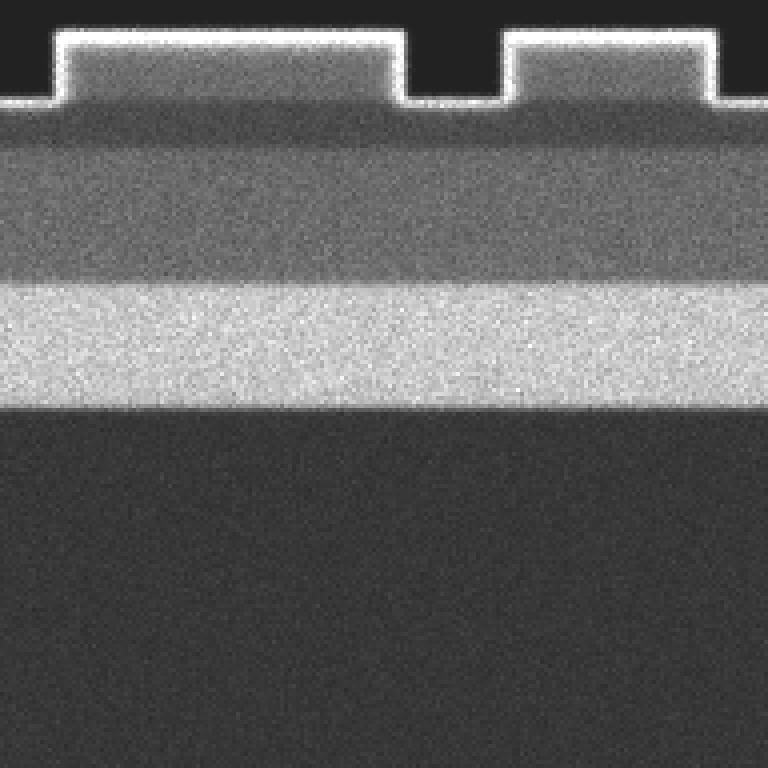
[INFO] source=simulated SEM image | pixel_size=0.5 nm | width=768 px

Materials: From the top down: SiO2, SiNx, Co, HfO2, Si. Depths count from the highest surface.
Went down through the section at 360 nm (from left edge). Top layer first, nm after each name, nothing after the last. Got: empty 34, SiNx 24, Co 68, HfO2 62, Si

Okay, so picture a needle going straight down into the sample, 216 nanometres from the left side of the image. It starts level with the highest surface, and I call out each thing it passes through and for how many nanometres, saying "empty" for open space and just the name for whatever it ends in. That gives empty 34, SiNx 24, Co 68, HfO2 62, Si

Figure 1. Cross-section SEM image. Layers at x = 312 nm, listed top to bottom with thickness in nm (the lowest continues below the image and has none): SiO2 34, SiNx 24, Co 68, HfO2 62, Si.